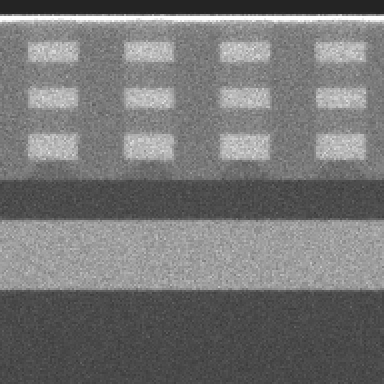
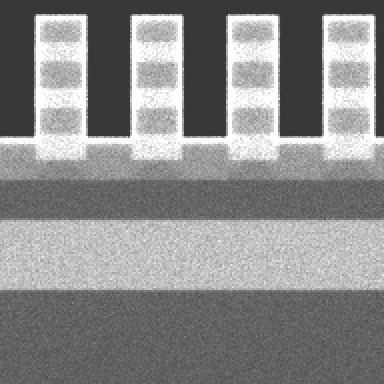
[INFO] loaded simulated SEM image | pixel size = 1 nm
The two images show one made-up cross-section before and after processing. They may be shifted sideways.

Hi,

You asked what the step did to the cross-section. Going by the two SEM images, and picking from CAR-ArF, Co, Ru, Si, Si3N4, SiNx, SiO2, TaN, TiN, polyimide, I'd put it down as Si3N4, removed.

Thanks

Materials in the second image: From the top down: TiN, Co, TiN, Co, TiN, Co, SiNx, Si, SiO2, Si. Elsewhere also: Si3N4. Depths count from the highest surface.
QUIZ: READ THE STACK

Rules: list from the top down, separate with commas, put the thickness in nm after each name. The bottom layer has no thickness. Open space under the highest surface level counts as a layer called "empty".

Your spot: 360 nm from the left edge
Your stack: TiN 26, Co 20, TiN 26, Co 20, TiN 26, Co 26, SiNx 20, Si 40, SiO2 70, Si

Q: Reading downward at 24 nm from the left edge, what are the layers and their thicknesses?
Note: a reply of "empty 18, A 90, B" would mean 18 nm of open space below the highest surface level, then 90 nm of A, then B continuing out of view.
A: empty 122, Si3N4 42, Si 40, SiO2 70, Si